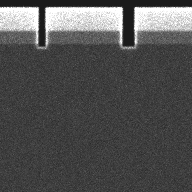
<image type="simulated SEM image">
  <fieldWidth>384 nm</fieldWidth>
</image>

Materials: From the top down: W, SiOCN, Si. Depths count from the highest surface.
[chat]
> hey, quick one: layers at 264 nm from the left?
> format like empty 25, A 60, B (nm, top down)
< empty 78, Si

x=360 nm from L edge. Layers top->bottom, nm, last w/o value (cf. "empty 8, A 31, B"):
W 46, SiOCN 26, Si